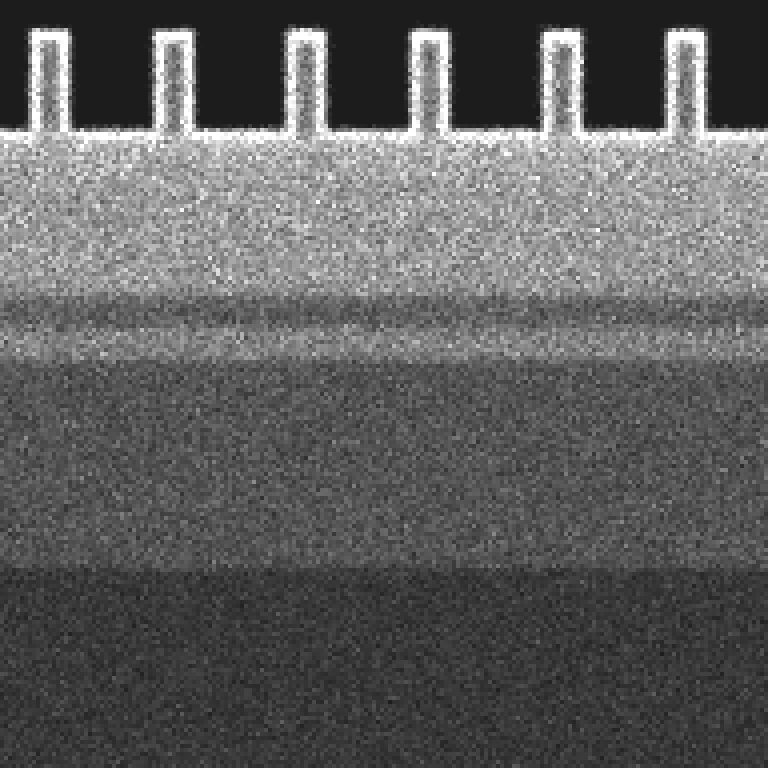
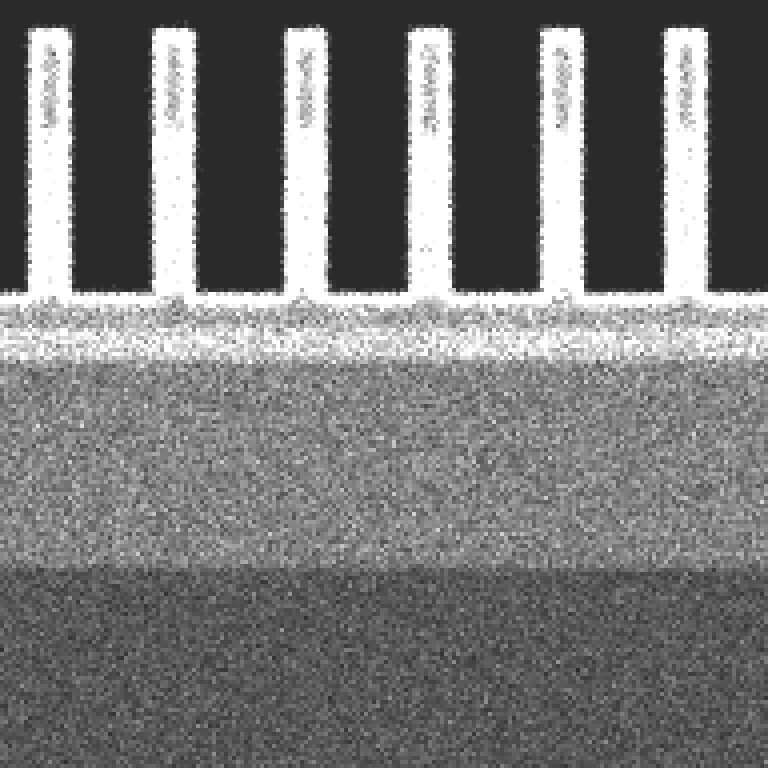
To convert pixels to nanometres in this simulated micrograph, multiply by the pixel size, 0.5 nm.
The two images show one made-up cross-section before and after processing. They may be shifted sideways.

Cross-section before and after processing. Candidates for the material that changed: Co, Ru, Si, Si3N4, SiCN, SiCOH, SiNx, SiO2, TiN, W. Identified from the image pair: Ru (removed).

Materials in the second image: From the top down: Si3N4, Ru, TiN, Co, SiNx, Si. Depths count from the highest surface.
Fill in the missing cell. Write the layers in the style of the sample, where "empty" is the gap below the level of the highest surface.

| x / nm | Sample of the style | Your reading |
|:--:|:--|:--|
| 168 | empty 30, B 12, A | empty 132, TiN 16, Co 16, SiNx 104, Si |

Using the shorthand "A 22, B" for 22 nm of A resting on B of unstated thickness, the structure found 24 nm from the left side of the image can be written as Si3N4 50, Ru 82, TiN 16, Co 16, SiNx 104, Si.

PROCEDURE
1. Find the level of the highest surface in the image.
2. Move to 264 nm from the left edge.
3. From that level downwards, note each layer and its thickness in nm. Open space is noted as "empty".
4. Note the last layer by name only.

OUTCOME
empty 132, TiN 16, Co 16, SiNx 104, Si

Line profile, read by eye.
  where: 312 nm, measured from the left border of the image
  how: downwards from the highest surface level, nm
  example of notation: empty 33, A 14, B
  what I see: empty 132, TiN 16, Co 16, SiNx 104, Si